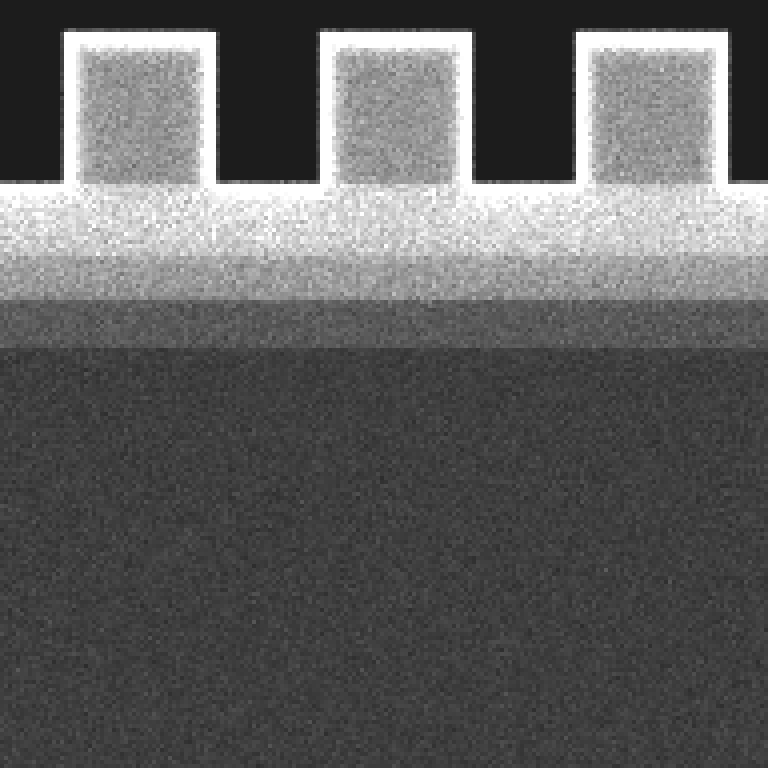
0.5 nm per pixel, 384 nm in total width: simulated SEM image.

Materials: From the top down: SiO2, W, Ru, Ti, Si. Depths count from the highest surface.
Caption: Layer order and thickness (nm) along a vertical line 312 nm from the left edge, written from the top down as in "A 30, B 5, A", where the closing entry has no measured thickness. SiO2 76, W 36, Ru 22, Ti 24, Si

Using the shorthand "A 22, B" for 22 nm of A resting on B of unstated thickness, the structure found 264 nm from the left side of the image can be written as empty 76, W 36, Ru 22, Ti 24, Si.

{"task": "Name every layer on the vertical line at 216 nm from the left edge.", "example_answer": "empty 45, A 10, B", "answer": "SiO2 76, W 36, Ru 22, Ti 24, Si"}